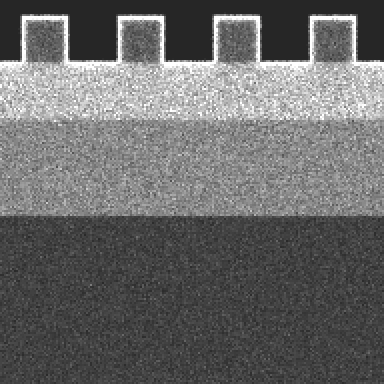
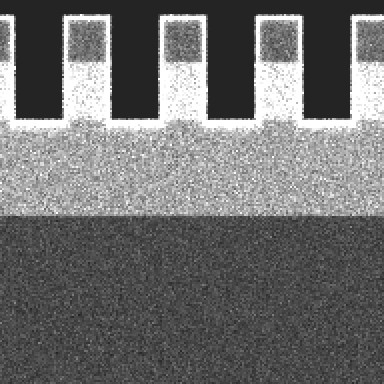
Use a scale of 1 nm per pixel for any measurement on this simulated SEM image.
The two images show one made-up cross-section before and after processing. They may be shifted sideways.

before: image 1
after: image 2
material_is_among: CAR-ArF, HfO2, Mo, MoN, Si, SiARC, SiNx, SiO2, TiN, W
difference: W, removed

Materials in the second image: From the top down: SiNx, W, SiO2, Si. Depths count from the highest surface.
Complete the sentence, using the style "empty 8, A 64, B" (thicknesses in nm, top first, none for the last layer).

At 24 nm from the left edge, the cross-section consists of empty 104, SiO2 96, Si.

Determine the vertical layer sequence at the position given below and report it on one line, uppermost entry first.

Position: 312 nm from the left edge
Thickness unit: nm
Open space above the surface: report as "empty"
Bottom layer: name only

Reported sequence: empty 104, SiO2 96, Si